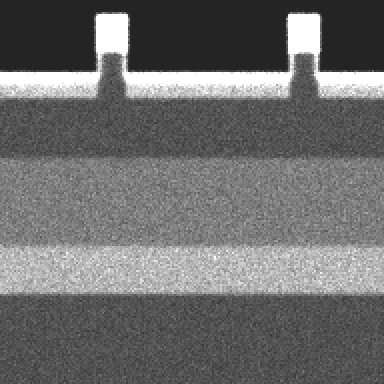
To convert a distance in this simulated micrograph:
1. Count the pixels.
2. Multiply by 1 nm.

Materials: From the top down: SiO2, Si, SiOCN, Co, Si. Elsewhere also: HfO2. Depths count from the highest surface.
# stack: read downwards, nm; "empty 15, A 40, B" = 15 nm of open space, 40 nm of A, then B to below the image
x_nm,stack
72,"empty 58, SiO2 24, Si 60, SiOCN 88, Co 48, Si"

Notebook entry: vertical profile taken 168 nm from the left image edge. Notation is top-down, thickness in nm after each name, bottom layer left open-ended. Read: empty 58, SiO2 24, Si 60, SiOCN 88, Co 48, Si